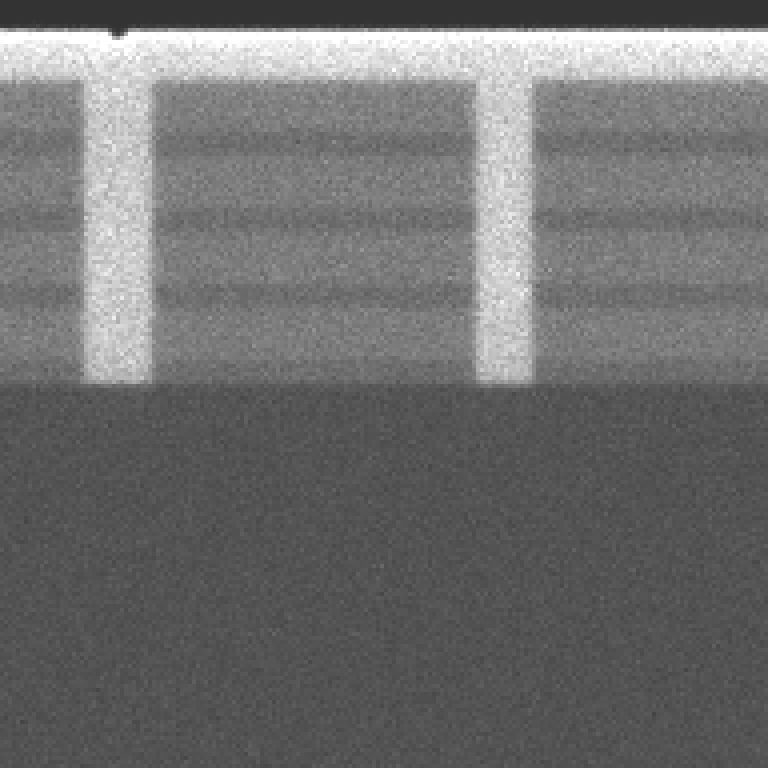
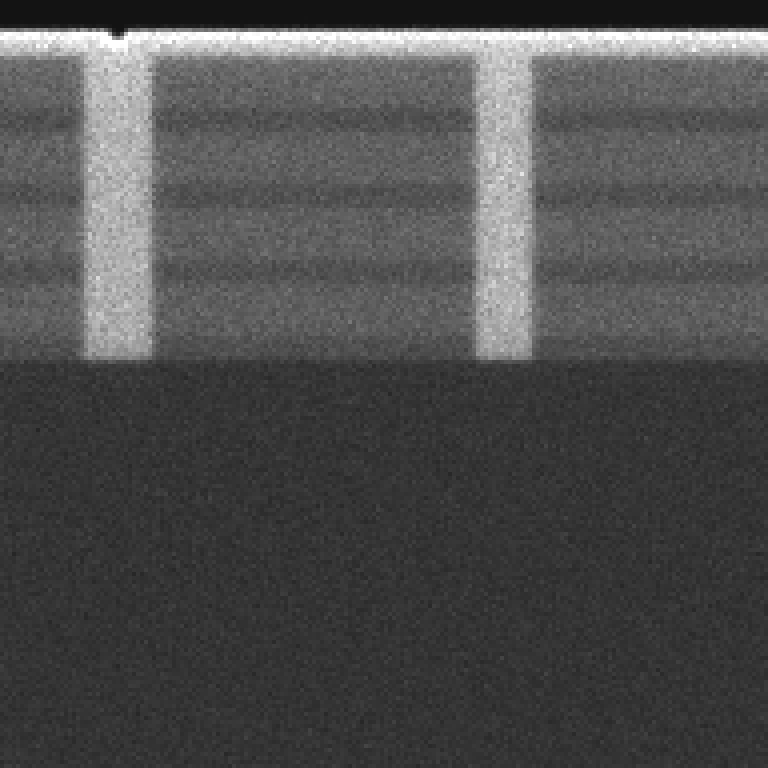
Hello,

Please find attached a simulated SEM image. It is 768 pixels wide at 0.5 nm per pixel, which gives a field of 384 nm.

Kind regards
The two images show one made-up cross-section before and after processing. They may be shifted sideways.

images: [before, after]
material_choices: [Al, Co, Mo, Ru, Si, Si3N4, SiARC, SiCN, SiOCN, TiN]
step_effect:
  removed: Ru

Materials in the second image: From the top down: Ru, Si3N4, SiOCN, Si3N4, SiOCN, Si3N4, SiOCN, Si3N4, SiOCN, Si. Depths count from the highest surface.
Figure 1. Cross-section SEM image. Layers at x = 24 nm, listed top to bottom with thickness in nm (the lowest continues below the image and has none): Ru 12, Si3N4 26, SiOCN 12, Si3N4 26, SiOCN 12, Si3N4 26, SiOCN 12, Si3N4 26, SiOCN 12, Si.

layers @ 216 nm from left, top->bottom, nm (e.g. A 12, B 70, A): Ru 12, Si3N4 26, SiOCN 12, Si3N4 26, SiOCN 12, Si3N4 26, SiOCN 12, Si3N4 26, SiOCN 12, Si